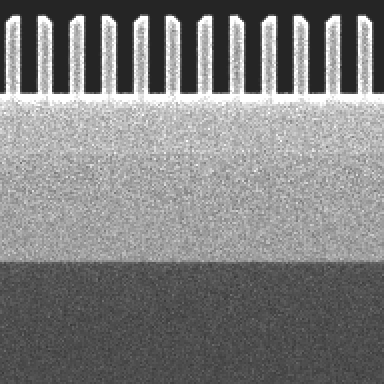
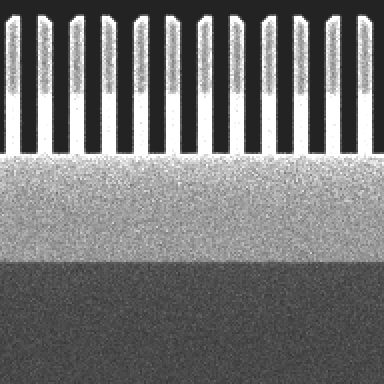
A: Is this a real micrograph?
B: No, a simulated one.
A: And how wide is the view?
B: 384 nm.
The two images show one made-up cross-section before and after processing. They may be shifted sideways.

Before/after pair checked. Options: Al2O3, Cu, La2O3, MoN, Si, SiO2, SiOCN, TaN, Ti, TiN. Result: removed Al2O3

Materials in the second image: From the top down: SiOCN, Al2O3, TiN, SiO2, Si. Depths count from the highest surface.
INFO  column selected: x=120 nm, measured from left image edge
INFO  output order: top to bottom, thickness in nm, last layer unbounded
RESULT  empty 138, TiN 48, SiO2 60, Si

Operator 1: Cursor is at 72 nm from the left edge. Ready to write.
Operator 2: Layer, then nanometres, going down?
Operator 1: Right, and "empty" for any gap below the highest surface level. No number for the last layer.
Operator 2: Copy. empty 4, SiOCN 74, Al2O3 60, TiN 48, SiO2 60, Si